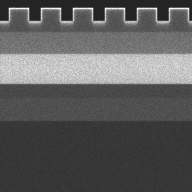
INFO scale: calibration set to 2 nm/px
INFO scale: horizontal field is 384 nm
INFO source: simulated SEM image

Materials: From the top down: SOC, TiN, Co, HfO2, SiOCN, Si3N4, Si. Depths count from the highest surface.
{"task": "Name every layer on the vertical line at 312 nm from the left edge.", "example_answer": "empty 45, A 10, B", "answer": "TiN 48, Co 44, HfO2 60, SiOCN 28, Si3N4 46, Si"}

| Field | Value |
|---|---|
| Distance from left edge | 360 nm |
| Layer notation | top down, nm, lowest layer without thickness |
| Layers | TiN 48, Co 44, HfO2 60, SiOCN 28, Si3N4 46, Si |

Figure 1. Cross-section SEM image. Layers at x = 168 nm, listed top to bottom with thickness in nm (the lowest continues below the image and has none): TiN 48, Co 44, HfO2 60, SiOCN 28, Si3N4 46, Si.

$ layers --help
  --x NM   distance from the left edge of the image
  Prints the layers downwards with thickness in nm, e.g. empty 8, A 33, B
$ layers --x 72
empty 26, SOC 16, TiN 6, Co 44, HfO2 60, SiOCN 28, Si3N4 46, Si